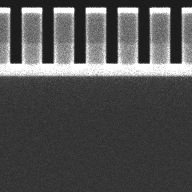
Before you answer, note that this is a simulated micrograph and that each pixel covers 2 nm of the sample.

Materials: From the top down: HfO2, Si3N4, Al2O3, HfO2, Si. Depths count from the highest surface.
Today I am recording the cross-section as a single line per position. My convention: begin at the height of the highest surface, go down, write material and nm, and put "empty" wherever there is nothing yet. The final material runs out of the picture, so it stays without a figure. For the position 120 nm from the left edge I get HfO2 10, Si3N4 60, Al2O3 42, HfO2 24, Si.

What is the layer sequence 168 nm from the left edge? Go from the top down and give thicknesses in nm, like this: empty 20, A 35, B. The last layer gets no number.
empty 112, HfO2 24, Si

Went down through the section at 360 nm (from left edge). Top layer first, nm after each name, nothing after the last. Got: empty 112, HfO2 24, Si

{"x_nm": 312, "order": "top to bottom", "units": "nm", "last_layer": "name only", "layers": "HfO2 10, Si3N4 60, Al2O3 42, HfO2 24, Si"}